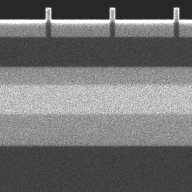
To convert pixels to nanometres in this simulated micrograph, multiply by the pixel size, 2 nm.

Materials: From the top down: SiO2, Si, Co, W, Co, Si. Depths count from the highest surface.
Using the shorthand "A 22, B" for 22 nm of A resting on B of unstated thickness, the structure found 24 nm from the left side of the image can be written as empty 24, SiO2 34, Si 60, Co 36, W 58, Co 64, Si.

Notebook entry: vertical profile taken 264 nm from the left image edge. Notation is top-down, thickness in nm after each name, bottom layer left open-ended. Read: empty 24, SiO2 34, Si 60, Co 36, W 58, Co 64, Si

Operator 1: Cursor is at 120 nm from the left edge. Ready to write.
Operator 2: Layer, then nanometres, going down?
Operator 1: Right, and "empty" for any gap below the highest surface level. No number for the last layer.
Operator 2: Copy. empty 24, SiO2 34, Si 60, Co 36, W 58, Co 64, Si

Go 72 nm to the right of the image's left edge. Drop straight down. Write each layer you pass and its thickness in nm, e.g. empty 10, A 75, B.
empty 24, SiO2 34, Si 60, Co 36, W 58, Co 64, Si